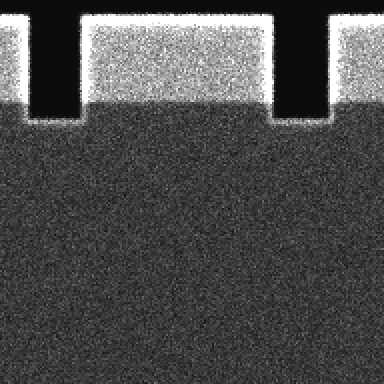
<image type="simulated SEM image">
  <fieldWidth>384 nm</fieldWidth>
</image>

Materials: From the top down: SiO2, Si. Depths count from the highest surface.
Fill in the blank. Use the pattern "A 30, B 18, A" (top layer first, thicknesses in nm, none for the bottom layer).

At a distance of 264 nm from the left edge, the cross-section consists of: SiO2 86, Si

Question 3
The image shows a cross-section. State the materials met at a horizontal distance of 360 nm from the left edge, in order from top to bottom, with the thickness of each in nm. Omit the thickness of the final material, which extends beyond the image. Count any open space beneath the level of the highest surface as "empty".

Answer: SiO2 86, Si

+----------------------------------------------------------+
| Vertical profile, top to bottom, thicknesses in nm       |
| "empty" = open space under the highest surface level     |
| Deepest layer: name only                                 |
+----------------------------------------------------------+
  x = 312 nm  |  empty 104, Si